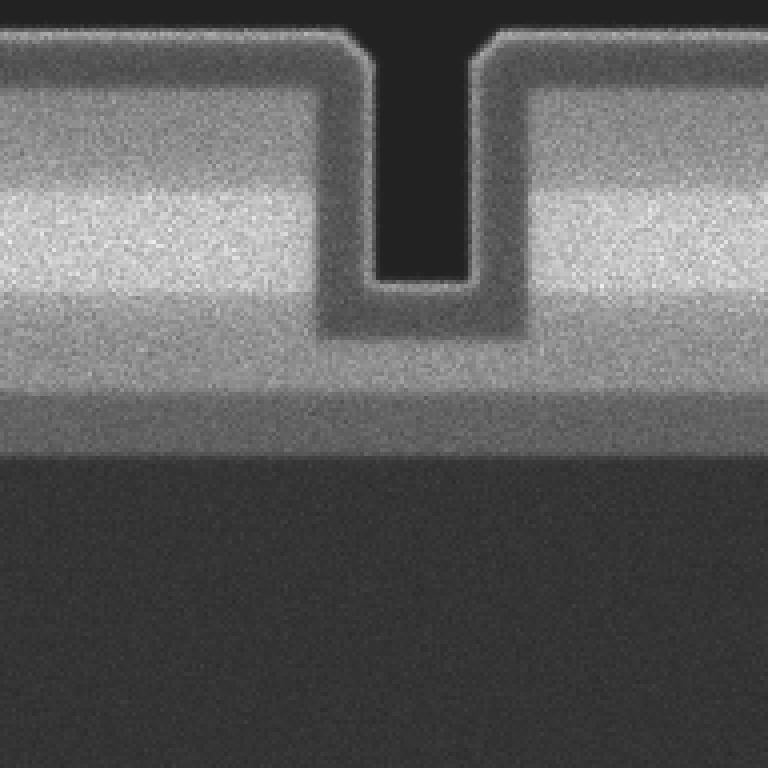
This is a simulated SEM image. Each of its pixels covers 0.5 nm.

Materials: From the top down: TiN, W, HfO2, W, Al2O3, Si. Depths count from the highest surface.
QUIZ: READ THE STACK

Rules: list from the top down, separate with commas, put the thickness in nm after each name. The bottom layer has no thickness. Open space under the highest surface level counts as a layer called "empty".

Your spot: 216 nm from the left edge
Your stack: empty 126, TiN 28, W 26, Al2O3 32, Si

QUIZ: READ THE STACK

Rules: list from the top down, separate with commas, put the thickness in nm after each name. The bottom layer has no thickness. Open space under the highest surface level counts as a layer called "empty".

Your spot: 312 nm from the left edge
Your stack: TiN 28, W 52, HfO2 50, W 50, Al2O3 32, Si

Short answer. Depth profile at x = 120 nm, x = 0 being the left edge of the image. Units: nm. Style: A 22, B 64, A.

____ TiN 28, W 52, HfO2 50, W 50, Al2O3 32, Si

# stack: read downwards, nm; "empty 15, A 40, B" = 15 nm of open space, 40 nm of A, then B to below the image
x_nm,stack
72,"TiN 28, W 52, HfO2 50, W 50, Al2O3 32, Si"